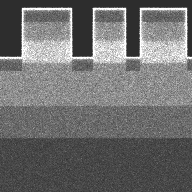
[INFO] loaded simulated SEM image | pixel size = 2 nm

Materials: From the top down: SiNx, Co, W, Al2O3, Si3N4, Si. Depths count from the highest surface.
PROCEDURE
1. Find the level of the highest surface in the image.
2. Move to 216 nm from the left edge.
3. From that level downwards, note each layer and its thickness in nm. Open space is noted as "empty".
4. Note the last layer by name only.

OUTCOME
SiNx 28, Co 38, W 44, Al2O3 86, Si3N4 64, Si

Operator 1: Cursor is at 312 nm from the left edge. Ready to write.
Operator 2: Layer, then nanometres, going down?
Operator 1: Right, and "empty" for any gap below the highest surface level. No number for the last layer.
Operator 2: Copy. SiNx 28, Co 38, W 44, Al2O3 86, Si3N4 64, Si